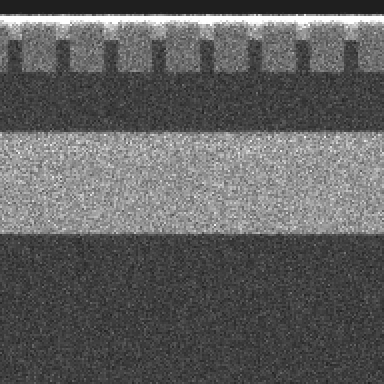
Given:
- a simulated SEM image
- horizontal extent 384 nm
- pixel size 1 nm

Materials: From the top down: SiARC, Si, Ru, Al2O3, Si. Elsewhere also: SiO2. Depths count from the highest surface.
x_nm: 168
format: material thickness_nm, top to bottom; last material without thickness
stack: SiARC 56, Si 60, Ru 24, Al2O3 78, Si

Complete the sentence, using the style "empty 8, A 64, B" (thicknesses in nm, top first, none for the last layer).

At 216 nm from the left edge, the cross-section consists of SiARC 56, Si 60, Ru 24, Al2O3 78, Si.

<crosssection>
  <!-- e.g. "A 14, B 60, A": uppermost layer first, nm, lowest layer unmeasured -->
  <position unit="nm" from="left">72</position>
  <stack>SiARC 56, Si 60, Ru 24, Al2O3 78, Si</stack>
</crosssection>